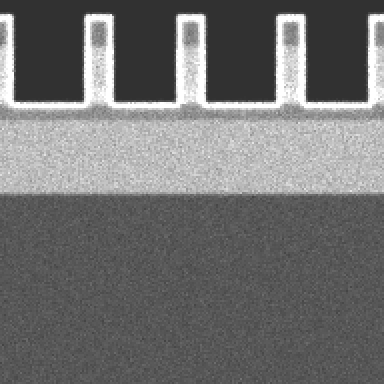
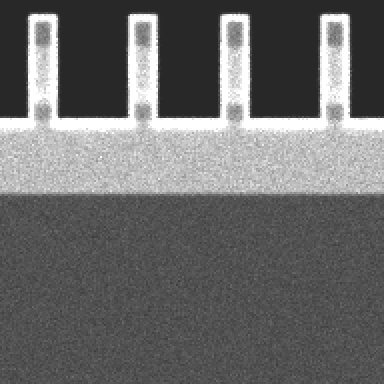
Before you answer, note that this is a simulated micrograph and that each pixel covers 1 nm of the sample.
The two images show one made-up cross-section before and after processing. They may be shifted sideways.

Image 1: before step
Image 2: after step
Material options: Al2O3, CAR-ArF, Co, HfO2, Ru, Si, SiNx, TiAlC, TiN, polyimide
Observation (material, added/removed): TiN, removed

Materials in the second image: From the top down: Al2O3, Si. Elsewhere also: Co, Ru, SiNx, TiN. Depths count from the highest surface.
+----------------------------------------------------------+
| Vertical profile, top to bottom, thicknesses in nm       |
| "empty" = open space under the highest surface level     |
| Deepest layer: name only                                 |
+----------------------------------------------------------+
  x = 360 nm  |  empty 104, Al2O3 74, Si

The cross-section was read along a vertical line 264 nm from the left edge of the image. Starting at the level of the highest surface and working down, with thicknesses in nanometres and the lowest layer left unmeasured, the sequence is empty 104, Al2O3 74, Si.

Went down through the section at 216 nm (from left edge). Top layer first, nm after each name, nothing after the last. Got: empty 104, Al2O3 74, Si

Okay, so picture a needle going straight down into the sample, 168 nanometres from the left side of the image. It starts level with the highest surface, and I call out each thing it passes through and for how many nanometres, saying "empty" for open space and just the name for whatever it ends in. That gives empty 104, Al2O3 74, Si